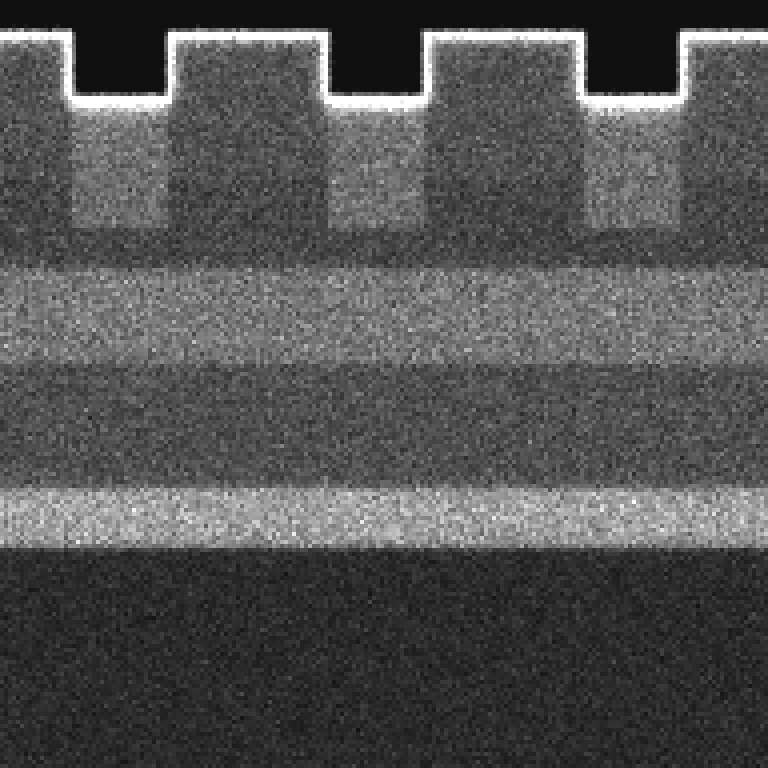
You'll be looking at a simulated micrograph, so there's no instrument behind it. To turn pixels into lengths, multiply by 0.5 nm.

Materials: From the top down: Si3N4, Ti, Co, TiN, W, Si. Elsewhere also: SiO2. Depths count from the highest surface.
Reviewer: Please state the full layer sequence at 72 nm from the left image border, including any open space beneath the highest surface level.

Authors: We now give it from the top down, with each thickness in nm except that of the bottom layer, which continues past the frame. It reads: empty 32, SiO2 66, Ti 20, Co 48, TiN 62, W 30, Si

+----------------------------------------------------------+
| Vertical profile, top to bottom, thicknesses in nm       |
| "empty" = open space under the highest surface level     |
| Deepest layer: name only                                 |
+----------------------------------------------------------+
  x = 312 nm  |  empty 32, SiO2 66, Ti 20, Co 48, TiN 62, W 30, Si